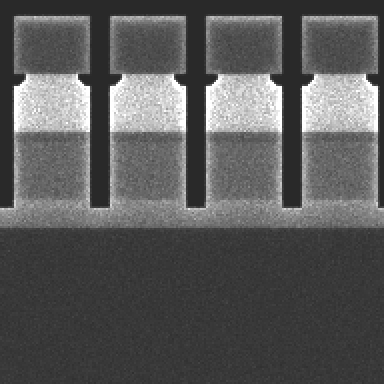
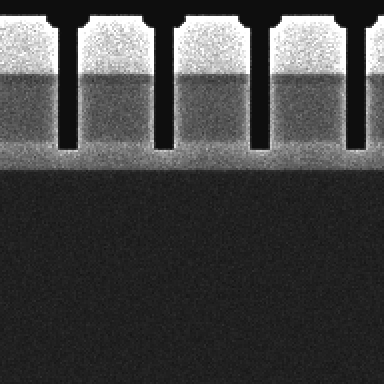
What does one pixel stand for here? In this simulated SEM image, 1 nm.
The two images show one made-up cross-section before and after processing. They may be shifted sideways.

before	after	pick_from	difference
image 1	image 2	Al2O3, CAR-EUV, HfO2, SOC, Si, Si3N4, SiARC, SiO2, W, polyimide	SOC removed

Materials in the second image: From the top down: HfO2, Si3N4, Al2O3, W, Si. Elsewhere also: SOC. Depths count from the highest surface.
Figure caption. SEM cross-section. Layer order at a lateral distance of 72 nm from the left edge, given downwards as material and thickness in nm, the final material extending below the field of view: empty 134, W 20, Si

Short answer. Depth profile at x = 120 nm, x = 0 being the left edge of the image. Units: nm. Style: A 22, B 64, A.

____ HfO2 58, Si3N4 10, Al2O3 58, W 28, Si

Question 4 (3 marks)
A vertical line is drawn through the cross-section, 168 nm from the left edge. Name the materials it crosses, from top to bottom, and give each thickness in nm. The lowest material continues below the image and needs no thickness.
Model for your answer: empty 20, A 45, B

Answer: empty 134, W 20, Si